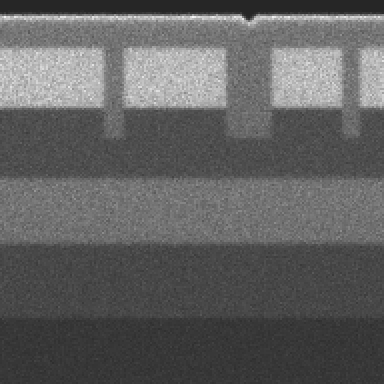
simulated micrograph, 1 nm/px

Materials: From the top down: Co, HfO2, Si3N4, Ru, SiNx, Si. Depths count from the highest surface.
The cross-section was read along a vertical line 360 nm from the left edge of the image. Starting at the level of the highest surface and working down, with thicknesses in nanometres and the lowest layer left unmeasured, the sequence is Co 32, HfO2 60, Si3N4 70, Ru 66, SiNx 74, Si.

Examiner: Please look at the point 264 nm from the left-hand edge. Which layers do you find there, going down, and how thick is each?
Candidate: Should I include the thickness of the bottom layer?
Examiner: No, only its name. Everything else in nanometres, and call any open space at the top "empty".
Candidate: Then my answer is Co 122, Si3N4 40, Ru 66, SiNx 74, Si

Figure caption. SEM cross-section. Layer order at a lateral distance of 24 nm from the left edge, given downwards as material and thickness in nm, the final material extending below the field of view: Co 32, HfO2 60, Si3N4 70, Ru 66, SiNx 74, Si